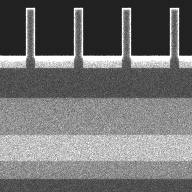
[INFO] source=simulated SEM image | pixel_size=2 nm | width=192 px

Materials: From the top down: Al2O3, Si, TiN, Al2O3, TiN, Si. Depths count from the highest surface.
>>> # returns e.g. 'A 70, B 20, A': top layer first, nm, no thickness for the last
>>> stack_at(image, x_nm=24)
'empty 96, Al2O3 24, Si 60, TiN 74, Al2O3 52, TiN 36, Si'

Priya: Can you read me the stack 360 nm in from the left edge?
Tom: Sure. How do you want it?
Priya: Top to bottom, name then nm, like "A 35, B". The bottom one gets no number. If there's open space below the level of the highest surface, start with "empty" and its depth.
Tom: empty 96, Al2O3 24, Si 60, TiN 74, Al2O3 52, TiN 36, Si